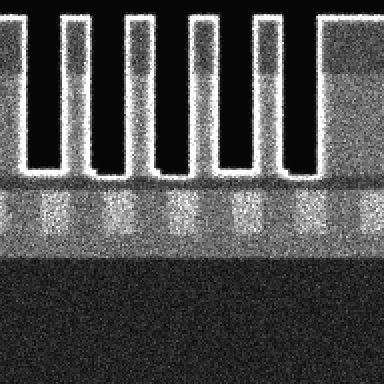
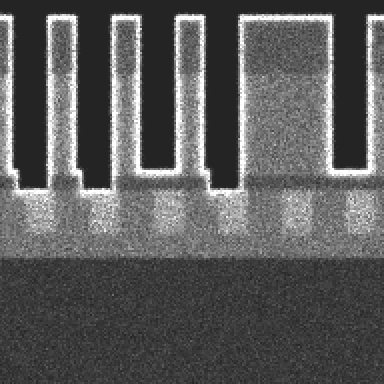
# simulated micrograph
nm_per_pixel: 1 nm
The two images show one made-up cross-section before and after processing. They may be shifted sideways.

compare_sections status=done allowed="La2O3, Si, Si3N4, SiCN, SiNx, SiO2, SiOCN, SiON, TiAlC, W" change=removed material="SiNx"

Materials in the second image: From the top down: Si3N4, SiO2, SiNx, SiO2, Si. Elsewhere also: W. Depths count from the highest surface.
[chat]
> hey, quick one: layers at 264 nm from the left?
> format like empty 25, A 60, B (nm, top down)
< Si3N4 58, SiO2 102, SiNx 14, SiO2 68, Si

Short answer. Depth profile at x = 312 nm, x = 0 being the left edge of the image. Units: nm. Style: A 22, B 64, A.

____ Si3N4 58, SiO2 102, SiNx 14, SiO2 68, Si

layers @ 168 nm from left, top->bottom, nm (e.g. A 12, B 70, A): empty 154, SiO2 6, SiNx 14, W 44, SiO2 24, Si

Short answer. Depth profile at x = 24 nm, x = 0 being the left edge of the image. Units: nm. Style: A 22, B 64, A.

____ empty 174, SiO2 68, Si